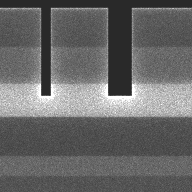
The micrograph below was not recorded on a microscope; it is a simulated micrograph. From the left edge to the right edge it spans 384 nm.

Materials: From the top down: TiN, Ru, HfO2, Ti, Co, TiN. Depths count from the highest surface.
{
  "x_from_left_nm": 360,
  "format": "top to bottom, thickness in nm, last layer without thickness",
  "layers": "TiN 78, Ru 74, HfO2 66, Ti 78, Co 40, TiN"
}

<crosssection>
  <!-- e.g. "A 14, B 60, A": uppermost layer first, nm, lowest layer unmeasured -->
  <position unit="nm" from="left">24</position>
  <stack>TiN 78, Ru 74, HfO2 66, Ti 78, Co 40, TiN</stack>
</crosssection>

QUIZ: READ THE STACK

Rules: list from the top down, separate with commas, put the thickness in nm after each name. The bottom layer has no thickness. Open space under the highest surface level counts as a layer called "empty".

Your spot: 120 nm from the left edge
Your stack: TiN 78, Ru 74, HfO2 66, Ti 78, Co 40, TiN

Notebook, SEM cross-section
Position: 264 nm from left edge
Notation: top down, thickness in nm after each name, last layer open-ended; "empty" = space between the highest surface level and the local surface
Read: TiN 78, Ru 74, HfO2 66, Ti 78, Co 40, TiN